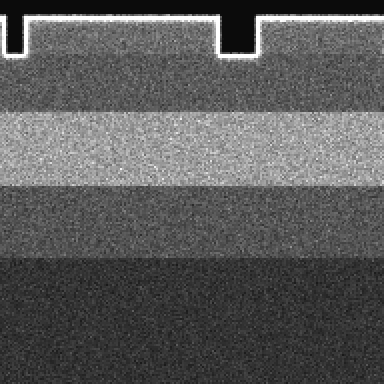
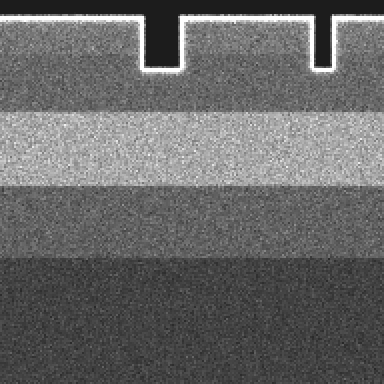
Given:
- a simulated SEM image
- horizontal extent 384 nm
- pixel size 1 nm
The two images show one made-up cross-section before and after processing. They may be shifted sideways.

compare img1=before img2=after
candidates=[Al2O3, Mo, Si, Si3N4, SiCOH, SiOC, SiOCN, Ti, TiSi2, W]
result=removed:SiOCN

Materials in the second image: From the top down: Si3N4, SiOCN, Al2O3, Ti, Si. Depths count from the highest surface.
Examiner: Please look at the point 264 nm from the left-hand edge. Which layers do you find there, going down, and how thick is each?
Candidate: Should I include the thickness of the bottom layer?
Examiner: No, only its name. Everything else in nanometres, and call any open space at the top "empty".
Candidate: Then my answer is Si3N4 38, SiOCN 58, Al2O3 74, Ti 72, Si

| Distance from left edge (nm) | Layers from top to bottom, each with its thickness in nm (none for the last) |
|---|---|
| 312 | Si3N4 38, SiOCN 58, Al2O3 74, Ti 72, Si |